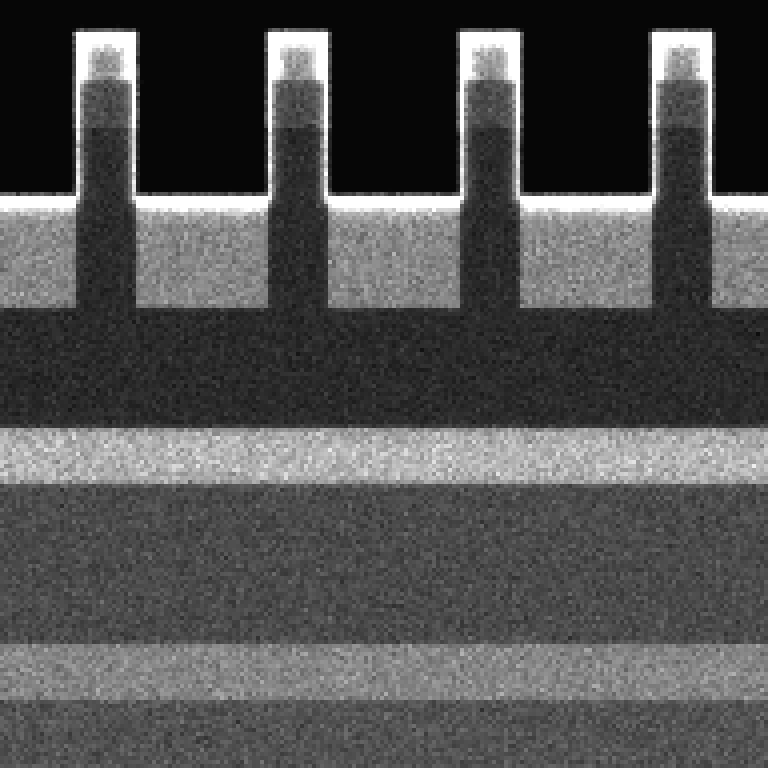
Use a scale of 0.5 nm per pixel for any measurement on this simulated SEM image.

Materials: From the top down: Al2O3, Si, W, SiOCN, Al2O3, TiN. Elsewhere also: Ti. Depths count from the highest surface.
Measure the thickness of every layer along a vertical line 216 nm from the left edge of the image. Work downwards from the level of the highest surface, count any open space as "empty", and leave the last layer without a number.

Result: empty 82, Al2O3 56, Si 60, W 28, SiOCN 80, Al2O3 28, TiN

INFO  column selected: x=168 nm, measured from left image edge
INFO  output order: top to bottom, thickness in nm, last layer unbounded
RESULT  empty 82, Al2O3 56, Si 60, W 28, SiOCN 80, Al2O3 28, TiN